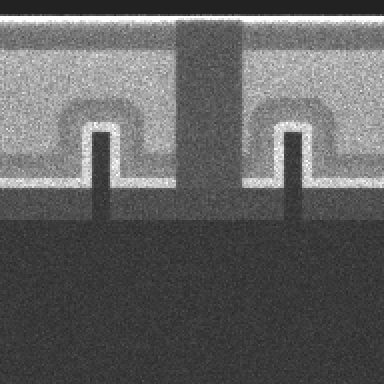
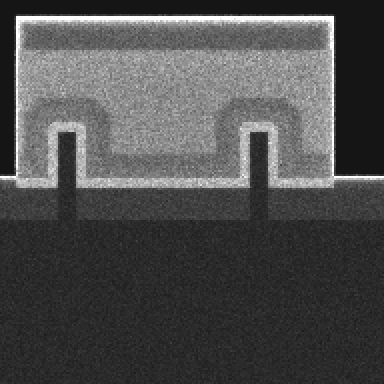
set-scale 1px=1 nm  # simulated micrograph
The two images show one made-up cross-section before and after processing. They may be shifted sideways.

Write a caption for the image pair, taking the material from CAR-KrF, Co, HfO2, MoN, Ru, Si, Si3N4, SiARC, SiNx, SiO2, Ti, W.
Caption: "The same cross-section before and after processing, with Si3N4 removed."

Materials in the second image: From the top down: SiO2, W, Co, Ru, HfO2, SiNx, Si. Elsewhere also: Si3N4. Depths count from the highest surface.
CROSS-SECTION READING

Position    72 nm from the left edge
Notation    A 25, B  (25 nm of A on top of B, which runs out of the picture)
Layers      SiO2 34, W 48, Co 12, Ru 12, HfO2 10, Si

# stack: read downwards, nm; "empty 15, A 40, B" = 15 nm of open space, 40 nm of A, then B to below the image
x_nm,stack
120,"SiO2 34, W 104, Co 12, Ru 12, HfO2 10, SiNx 32, Si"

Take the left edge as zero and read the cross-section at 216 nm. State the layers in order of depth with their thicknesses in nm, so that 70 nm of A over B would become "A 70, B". SiO2 34, W 64, Co 52, Ru 12, HfO2 10, SiNx 32, Si